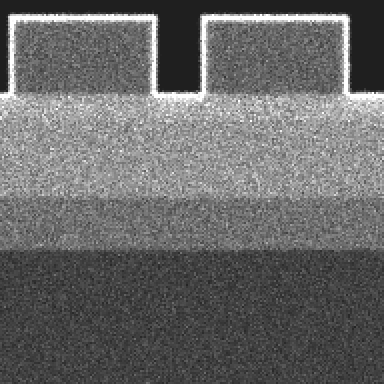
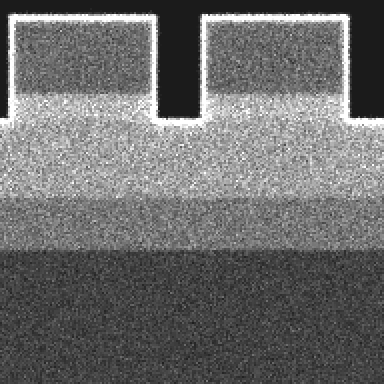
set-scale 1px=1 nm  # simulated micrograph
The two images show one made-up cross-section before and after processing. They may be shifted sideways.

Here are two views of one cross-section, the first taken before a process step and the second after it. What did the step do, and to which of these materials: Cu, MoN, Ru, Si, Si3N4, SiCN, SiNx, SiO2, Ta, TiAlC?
It removed Ru.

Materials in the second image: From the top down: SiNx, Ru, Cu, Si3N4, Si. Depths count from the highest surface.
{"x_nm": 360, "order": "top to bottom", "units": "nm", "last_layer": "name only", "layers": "empty 104, Cu 78, Si3N4 52, Si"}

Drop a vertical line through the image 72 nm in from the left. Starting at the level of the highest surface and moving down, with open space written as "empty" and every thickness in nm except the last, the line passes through SiNx 78, Ru 26, Cu 78, Si3N4 52, Si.